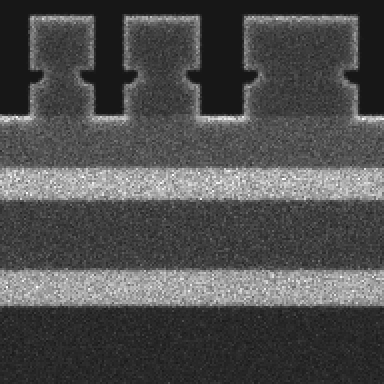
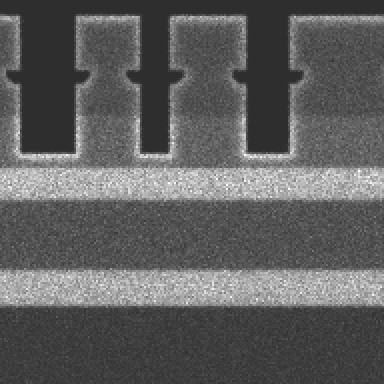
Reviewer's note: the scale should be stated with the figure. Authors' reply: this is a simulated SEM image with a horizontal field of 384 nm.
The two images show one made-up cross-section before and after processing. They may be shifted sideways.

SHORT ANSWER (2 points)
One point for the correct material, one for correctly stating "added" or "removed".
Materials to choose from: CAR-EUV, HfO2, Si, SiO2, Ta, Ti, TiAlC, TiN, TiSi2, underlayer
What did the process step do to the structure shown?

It removed SiO2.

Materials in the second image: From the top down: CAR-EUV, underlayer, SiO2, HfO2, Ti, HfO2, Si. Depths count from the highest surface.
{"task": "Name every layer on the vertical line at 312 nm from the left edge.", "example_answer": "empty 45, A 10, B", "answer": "CAR-EUV 54, underlayer 46, SiO2 52, HfO2 32, Ti 70, HfO2 36, Si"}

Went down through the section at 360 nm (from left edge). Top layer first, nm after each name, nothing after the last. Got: CAR-EUV 54, underlayer 46, SiO2 52, HfO2 32, Ti 70, HfO2 36, Si